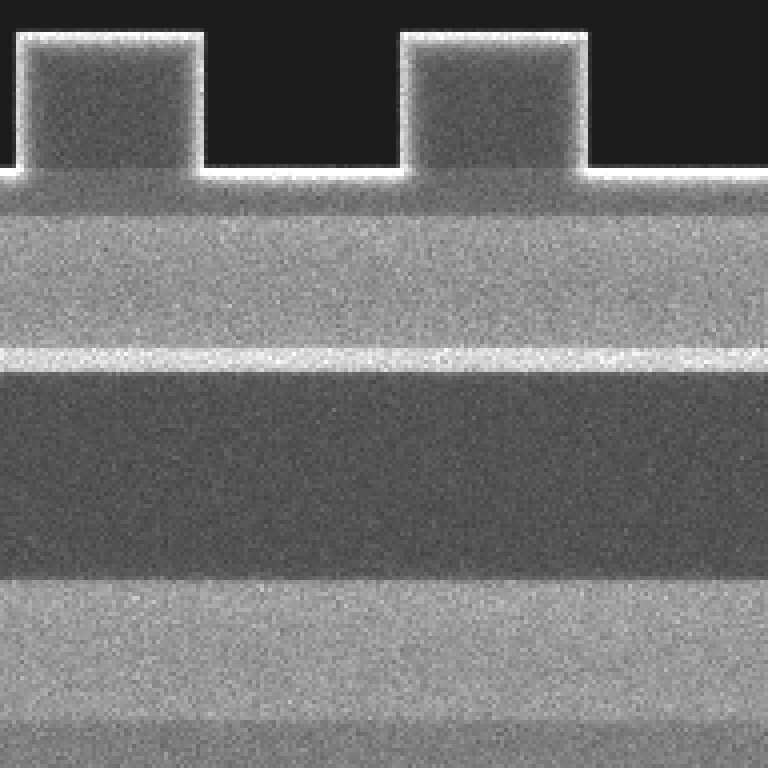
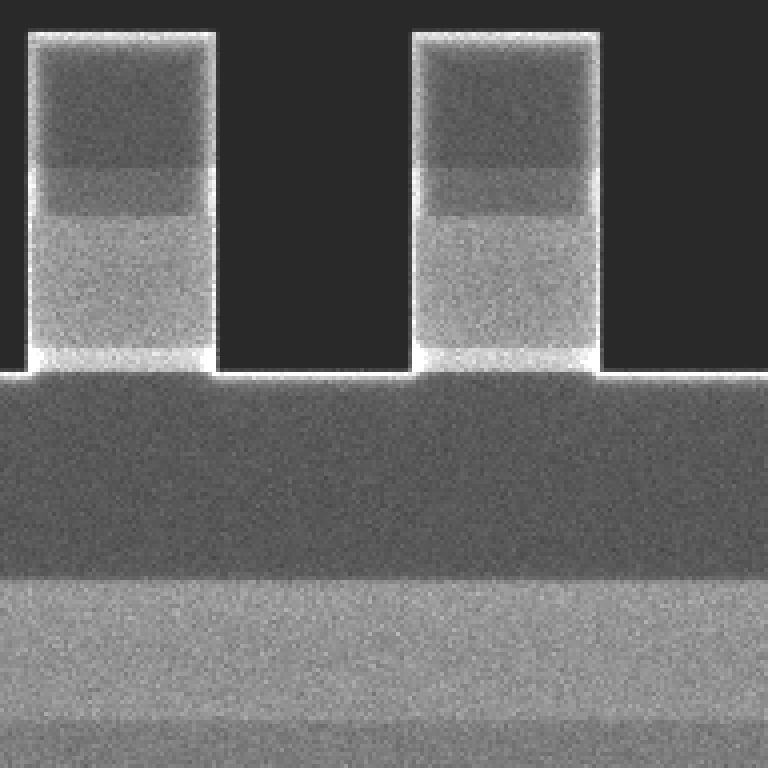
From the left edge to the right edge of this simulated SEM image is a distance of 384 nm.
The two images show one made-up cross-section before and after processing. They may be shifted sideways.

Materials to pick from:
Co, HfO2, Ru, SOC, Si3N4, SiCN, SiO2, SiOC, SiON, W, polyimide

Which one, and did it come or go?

HfO2 and Ru and SiO2 - removed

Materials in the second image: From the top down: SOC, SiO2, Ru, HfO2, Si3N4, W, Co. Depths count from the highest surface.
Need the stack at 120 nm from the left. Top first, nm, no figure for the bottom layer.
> empty 170, Si3N4 104, W 70, Co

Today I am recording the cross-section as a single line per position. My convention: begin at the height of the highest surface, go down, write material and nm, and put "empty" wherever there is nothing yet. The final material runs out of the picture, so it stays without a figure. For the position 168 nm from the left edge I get empty 170, Si3N4 104, W 70, Co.